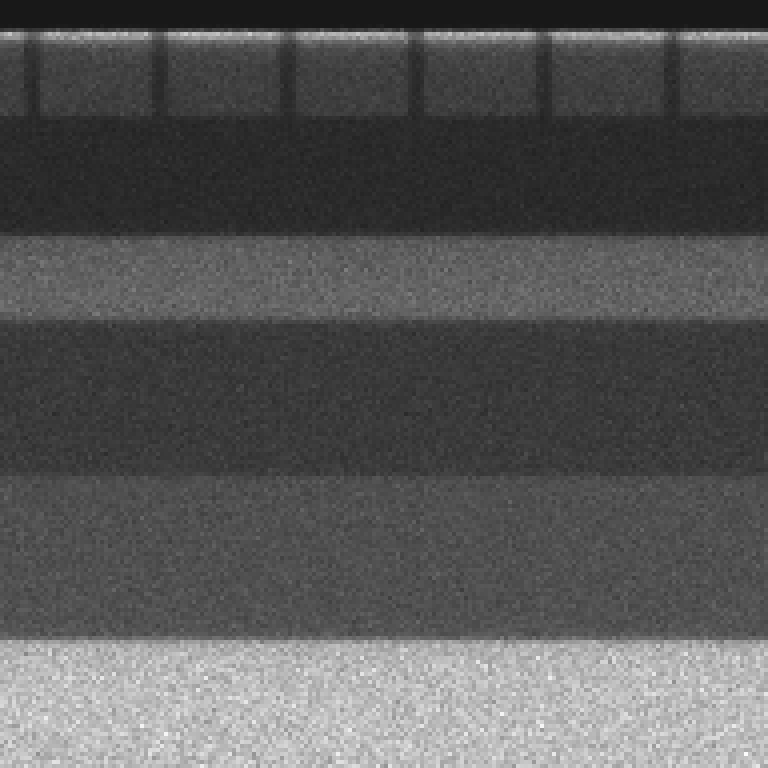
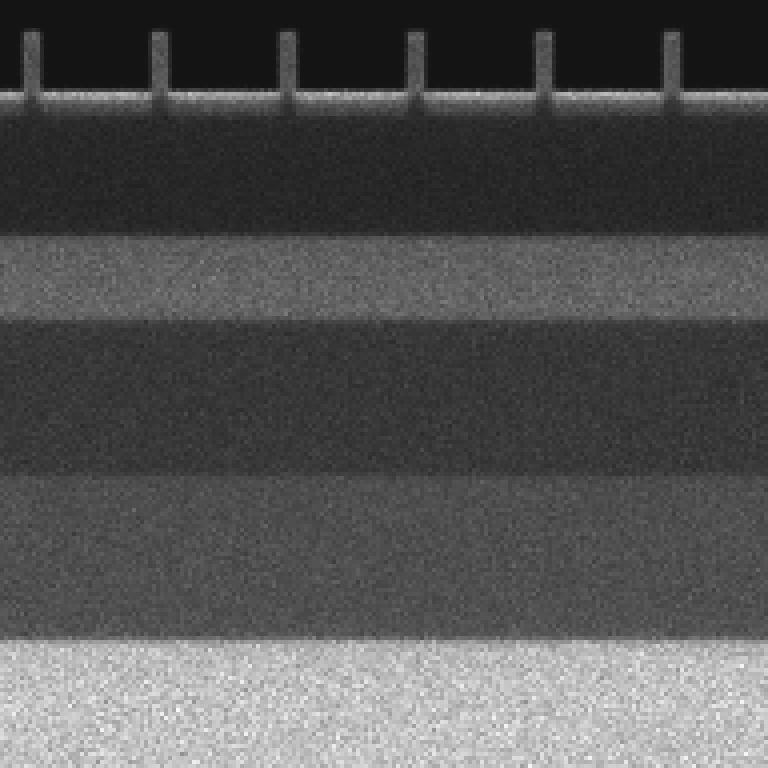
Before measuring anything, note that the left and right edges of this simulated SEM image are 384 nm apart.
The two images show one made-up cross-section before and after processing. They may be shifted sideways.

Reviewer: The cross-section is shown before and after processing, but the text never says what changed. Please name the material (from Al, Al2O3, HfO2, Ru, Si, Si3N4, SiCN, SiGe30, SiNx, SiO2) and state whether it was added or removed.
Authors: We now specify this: Si3N4, removed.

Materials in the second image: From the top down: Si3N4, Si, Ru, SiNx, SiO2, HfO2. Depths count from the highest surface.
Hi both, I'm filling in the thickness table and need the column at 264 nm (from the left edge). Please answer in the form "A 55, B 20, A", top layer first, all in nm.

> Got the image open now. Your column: empty 30, Si3N4 12, Si 60, Ru 42, SiNx 78, SiO2 82, HfO2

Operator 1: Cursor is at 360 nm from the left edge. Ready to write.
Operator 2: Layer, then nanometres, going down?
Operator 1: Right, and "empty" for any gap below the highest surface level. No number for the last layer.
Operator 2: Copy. empty 30, Si3N4 12, Si 60, Ru 42, SiNx 78, SiO2 82, HfO2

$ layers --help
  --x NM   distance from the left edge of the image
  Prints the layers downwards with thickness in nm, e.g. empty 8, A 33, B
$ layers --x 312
empty 30, Si3N4 12, Si 60, Ru 42, SiNx 78, SiO2 82, HfO2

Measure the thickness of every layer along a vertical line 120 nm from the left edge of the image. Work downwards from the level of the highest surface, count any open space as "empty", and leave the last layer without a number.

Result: empty 30, Si3N4 12, Si 60, Ru 42, SiNx 78, SiO2 82, HfO2